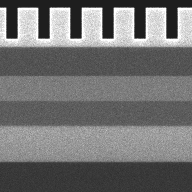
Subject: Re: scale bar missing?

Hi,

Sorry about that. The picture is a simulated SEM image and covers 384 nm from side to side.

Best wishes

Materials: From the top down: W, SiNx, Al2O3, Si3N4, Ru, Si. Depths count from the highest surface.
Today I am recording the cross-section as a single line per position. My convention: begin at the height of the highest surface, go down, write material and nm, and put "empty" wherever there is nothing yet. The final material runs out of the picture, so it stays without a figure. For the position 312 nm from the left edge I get W 78, SiNx 58, Al2O3 50, Si3N4 50, Ru 72, Si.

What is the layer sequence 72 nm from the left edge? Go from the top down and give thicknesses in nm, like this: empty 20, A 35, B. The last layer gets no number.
W 78, SiNx 58, Al2O3 50, Si3N4 50, Ru 72, Si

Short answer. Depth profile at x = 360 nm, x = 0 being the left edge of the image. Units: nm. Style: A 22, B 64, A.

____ W 78, SiNx 58, Al2O3 50, Si3N4 50, Ru 72, Si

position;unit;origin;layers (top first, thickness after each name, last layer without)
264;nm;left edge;W 78, SiNx 58, Al2O3 50, Si3N4 50, Ru 72, Si